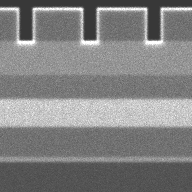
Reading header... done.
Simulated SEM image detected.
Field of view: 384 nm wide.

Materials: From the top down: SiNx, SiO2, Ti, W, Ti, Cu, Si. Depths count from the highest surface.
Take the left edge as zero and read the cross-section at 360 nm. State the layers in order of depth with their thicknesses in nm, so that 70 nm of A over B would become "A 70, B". SiNx 66, SiO2 68, Ti 48, W 56, Ti 60, Cu 10, Si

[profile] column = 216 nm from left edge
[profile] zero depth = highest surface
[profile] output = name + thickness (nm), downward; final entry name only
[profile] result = SiNx 66, SiO2 68, Ti 48, W 56, Ti 60, Cu 10, Si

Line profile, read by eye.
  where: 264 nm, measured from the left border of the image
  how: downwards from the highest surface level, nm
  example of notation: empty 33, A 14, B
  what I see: SiNx 66, SiO2 68, Ti 48, W 56, Ti 60, Cu 10, Si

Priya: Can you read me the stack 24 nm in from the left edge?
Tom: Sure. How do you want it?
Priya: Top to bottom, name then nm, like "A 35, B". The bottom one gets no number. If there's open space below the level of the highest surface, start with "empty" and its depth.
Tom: SiNx 66, SiO2 68, Ti 48, W 56, Ti 60, Cu 10, Si